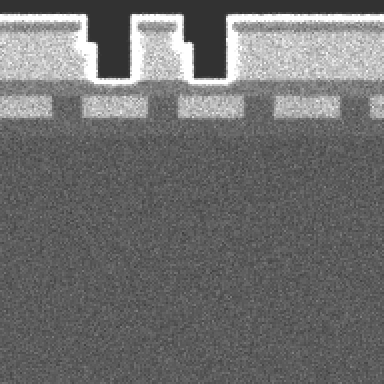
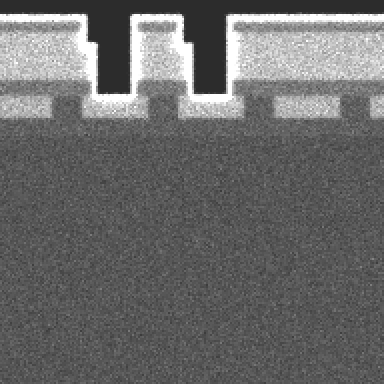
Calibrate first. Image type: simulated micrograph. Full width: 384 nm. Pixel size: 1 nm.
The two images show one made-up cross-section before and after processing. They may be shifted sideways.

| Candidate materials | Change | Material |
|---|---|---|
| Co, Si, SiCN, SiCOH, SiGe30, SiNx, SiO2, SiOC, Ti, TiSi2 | removed | SiCN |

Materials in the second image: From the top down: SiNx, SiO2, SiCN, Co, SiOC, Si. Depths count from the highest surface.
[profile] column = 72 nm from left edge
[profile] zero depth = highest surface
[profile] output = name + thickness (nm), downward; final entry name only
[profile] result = SiNx 16, SiO2 48, SiCN 16, SiOC 40, Si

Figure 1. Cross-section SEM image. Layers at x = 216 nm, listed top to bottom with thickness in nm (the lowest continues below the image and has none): empty 80, Co 22, SiOC 18, Si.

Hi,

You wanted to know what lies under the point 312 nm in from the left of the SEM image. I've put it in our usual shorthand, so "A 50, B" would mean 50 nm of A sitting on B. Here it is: SiNx 16, SiO2 48, SiCN 16, Co 22, SiOC 18, Si